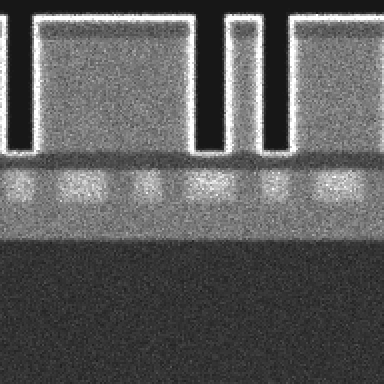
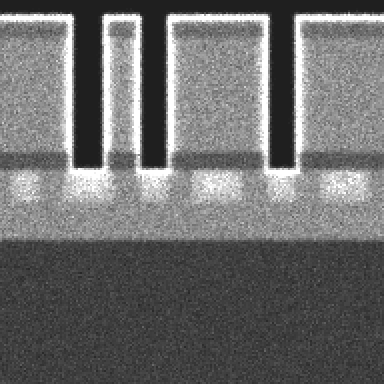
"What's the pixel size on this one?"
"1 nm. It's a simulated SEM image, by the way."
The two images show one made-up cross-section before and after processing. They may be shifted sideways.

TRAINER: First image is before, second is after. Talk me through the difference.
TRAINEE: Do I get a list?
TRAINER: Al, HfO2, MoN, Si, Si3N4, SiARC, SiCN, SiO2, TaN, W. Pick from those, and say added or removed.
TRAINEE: removed: SiCN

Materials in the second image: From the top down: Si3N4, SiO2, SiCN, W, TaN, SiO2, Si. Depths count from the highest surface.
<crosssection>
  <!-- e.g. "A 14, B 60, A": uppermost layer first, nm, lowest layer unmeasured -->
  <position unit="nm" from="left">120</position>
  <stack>Si3N4 22, SiO2 114, SiCN 18, SiO2 70, Si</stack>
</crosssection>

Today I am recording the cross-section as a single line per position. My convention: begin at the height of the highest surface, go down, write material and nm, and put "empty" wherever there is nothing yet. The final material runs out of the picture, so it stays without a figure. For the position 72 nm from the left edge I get empty 154, TaN 32, SiO2 38, Si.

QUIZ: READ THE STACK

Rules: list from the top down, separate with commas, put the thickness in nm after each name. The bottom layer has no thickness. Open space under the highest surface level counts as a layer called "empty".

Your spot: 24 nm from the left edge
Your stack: Si3N4 22, SiO2 114, SiCN 18, W 22, TaN 10, SiO2 38, Si